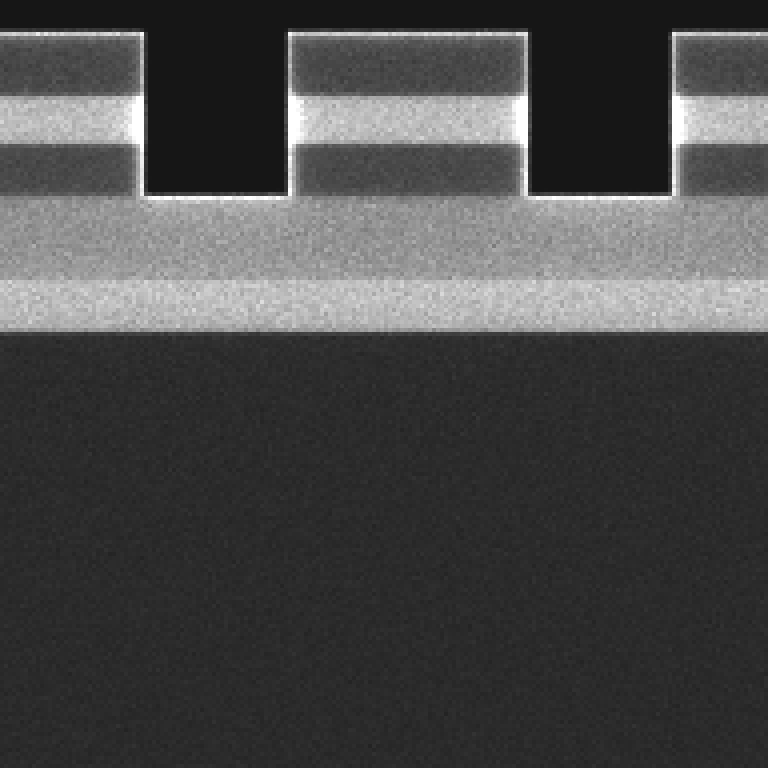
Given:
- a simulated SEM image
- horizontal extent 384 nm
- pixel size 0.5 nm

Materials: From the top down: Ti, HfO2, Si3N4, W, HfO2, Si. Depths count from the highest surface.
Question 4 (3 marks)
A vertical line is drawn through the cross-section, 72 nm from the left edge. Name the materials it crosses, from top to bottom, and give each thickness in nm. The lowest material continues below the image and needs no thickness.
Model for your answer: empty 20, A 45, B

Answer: empty 82, W 42, HfO2 26, Si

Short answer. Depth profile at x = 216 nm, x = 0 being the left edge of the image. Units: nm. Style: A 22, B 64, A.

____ Ti 32, HfO2 24, Si3N4 26, W 42, HfO2 26, Si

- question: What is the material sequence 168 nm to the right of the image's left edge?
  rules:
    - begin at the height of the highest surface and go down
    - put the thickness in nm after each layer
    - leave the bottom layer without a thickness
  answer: Ti 32, HfO2 24, Si3N4 26, W 42, HfO2 26, Si